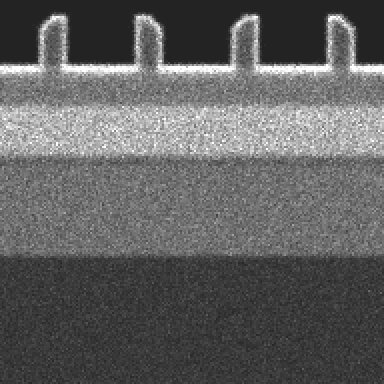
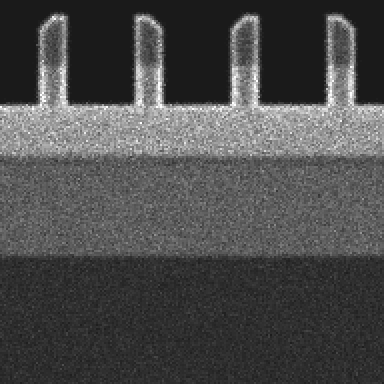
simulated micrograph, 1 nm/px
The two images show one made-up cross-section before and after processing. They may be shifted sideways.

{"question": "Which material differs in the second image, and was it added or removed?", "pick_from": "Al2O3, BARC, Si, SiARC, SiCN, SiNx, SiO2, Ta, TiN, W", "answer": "Al2O3, removed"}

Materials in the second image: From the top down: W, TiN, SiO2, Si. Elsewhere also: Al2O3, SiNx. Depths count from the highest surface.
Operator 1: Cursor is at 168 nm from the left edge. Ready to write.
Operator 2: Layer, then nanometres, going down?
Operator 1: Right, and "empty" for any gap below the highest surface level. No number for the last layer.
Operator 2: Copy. empty 90, W 50, TiN 10, SiO2 90, Si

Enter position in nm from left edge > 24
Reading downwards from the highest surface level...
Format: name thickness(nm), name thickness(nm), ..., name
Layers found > empty 90, W 50, TiN 10, SiO2 90, Si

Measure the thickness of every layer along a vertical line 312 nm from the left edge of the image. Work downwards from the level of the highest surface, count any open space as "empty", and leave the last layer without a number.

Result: empty 90, W 50, TiN 10, SiO2 90, Si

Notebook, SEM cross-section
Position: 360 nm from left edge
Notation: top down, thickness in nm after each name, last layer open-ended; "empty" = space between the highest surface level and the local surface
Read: empty 90, W 50, TiN 10, SiO2 90, Si